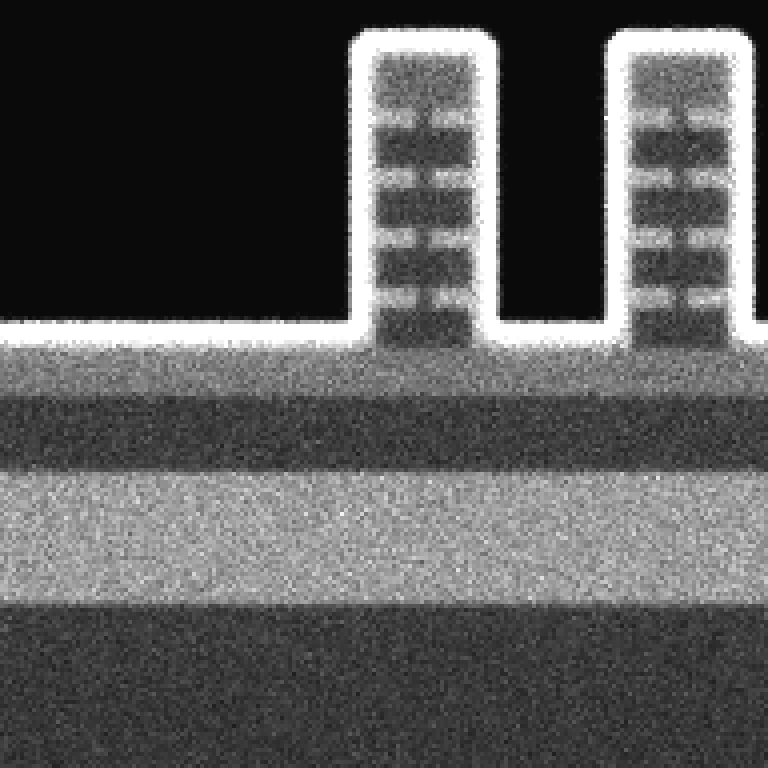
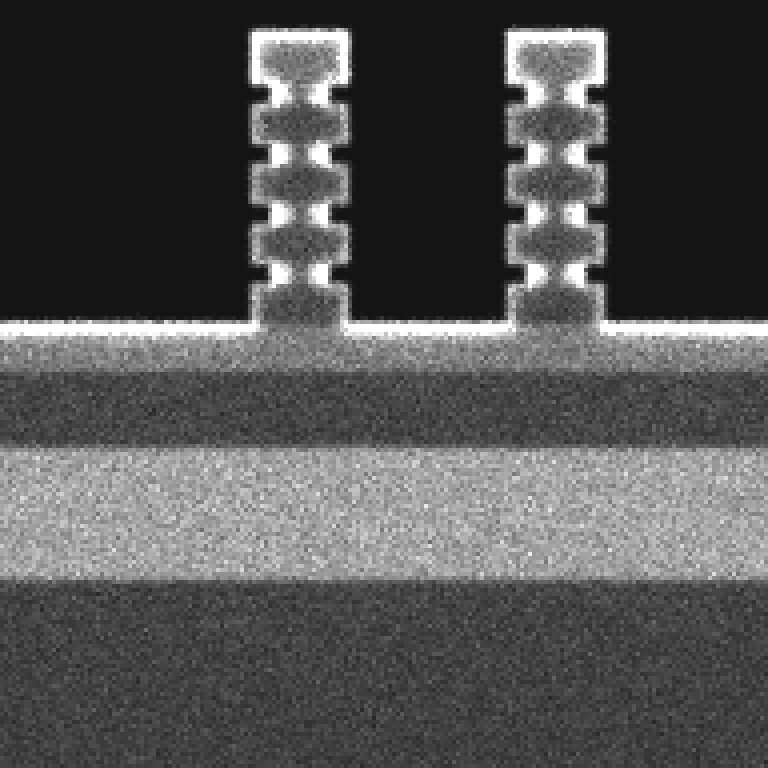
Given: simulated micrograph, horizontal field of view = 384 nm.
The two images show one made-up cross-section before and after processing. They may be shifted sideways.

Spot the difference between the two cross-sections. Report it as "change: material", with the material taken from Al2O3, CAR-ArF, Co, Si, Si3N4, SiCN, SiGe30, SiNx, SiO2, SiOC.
removed: Al2O3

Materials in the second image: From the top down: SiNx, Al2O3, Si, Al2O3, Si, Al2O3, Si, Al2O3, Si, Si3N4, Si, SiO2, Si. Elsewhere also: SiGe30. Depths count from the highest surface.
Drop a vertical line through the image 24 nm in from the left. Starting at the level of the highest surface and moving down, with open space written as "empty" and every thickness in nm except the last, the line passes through empty 146, Si3N4 24, Si 38, SiO2 66, Si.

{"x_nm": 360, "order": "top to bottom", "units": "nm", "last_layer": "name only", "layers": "empty 146, Si3N4 24, Si 38, SiO2 66, Si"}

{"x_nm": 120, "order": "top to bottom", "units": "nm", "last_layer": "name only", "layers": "empty 146, Si3N4 24, Si 38, SiO2 66, Si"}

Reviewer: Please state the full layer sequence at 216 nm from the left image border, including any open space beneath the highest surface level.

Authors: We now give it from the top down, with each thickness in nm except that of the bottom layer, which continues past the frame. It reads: empty 146, Si3N4 24, Si 38, SiO2 66, Si